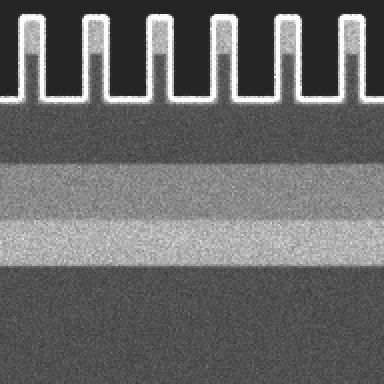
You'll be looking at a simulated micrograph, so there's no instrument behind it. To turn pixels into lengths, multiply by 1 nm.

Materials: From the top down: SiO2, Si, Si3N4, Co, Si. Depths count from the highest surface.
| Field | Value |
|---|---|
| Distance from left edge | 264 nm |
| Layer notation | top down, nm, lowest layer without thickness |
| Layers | empty 82, Si 66, Si3N4 56, Co 46, Si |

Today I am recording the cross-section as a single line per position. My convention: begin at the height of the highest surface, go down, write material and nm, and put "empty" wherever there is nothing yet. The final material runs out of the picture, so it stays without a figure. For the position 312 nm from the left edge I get empty 82, Si 66, Si3N4 56, Co 46, Si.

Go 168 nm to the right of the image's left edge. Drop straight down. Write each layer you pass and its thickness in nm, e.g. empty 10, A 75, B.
SiO2 38, Si 110, Si3N4 56, Co 46, Si